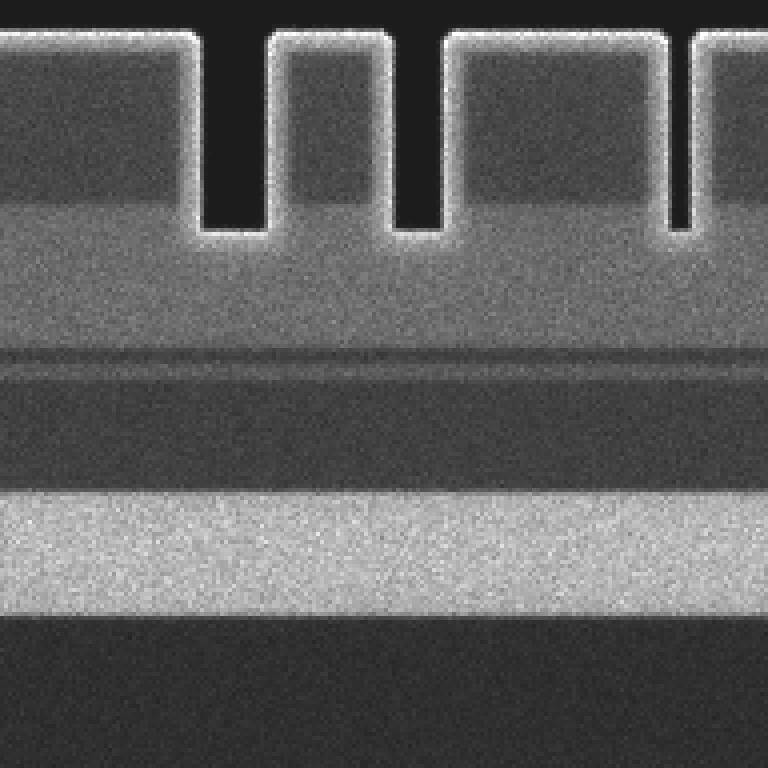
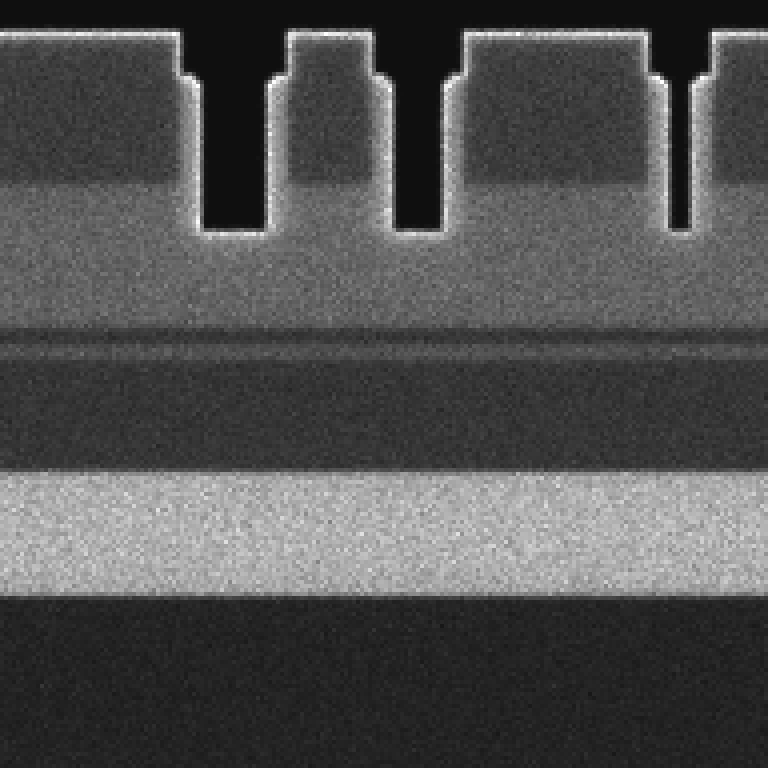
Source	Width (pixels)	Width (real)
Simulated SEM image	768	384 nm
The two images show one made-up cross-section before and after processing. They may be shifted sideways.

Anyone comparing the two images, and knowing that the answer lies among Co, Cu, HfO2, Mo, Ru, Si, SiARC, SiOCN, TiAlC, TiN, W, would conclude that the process removed W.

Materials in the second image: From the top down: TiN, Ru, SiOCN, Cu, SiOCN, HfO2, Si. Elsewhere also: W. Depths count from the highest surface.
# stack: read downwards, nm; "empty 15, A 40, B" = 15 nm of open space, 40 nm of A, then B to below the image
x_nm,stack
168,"TiN 76, Ru 72, SiOCN 8, Cu 8, SiOCN 56, HfO2 62, Si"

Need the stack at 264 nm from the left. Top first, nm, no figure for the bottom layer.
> TiN 76, Ru 72, SiOCN 8, Cu 8, SiOCN 56, HfO2 62, Si